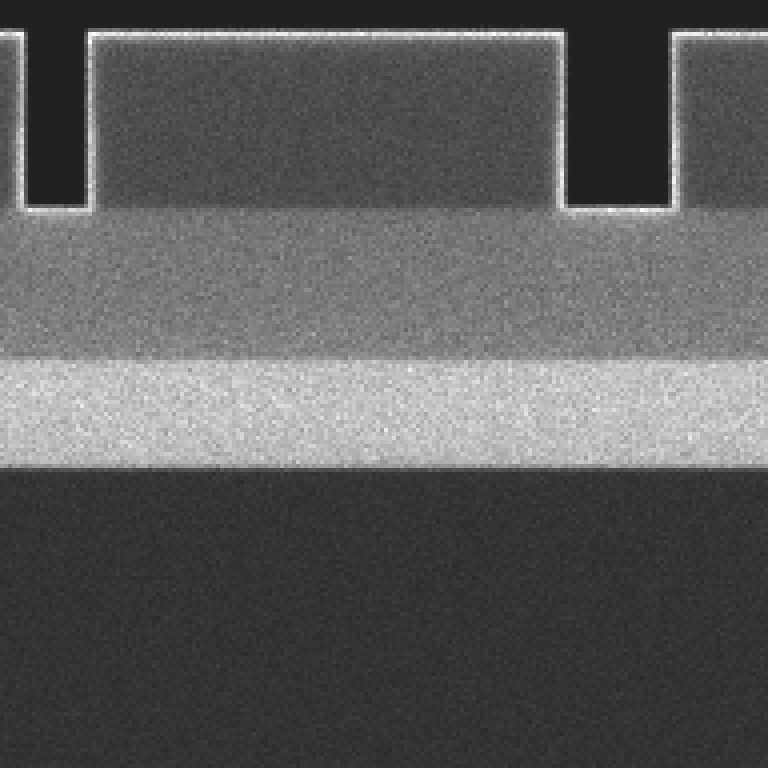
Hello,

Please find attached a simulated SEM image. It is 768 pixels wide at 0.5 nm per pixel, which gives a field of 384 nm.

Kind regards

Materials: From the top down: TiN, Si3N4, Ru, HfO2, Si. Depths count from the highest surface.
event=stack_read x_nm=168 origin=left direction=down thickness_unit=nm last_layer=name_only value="TiN 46, Si3N4 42, Ru 76, HfO2 54, Si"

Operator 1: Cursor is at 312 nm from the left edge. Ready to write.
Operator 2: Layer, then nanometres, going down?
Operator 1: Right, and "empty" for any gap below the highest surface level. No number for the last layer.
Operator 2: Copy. empty 88, Ru 76, HfO2 54, Si